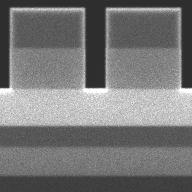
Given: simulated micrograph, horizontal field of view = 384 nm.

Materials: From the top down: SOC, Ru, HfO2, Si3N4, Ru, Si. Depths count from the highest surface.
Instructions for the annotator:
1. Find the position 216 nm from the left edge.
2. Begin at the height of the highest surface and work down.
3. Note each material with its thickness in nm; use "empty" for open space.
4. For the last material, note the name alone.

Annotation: SOC 80, Ru 82, HfO2 74, Si3N4 42, Ru 58, Si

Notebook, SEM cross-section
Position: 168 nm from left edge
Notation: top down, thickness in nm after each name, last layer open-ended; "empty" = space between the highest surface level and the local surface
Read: SOC 80, Ru 82, HfO2 74, Si3N4 42, Ru 58, Si